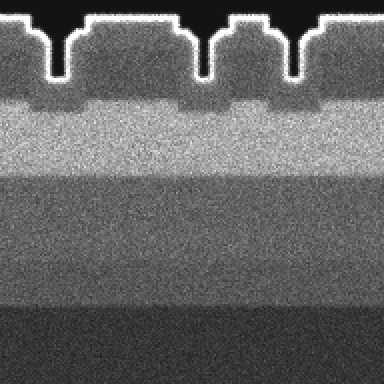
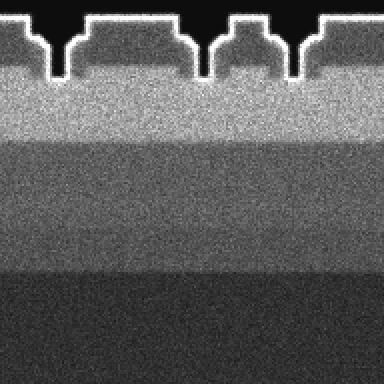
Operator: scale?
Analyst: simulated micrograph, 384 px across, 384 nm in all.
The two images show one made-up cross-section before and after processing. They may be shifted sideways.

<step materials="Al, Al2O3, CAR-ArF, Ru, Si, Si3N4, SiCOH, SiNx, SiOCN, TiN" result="removed Si3N4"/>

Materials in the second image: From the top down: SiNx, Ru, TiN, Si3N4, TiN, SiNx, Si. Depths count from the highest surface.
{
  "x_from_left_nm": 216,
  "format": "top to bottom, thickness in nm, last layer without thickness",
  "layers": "empty 24, Si3N4 38, Ru 64, TiN 54, Si3N4 16, TiN 16, SiNx 44, Si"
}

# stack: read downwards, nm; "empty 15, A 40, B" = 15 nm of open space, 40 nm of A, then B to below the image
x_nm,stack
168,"SiNx 50, Ru 76, TiN 54, Si3N4 16, TiN 16, SiNx 44, Si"